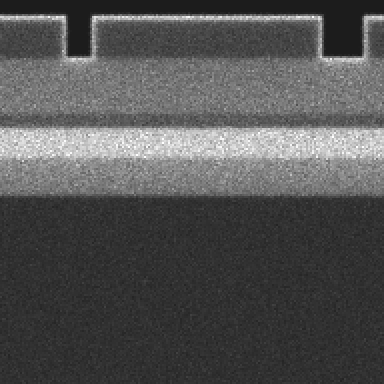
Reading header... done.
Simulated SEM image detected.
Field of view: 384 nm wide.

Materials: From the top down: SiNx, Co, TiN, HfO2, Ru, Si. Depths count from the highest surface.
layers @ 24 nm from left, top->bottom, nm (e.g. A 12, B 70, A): SiNx 42, Co 56, TiN 14, HfO2 30, Ru 38, Si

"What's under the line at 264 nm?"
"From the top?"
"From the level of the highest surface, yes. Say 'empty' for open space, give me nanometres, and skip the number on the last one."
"SiNx 42, Co 56, TiN 14, HfO2 30, Ru 38, Si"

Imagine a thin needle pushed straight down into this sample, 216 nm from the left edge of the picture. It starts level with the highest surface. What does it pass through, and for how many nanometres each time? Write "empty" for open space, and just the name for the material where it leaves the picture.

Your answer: SiNx 42, Co 56, TiN 14, HfO2 30, Ru 38, Si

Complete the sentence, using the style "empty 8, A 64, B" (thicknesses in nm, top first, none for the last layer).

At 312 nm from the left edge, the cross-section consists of SiNx 42, Co 56, TiN 14, HfO2 30, Ru 38, Si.